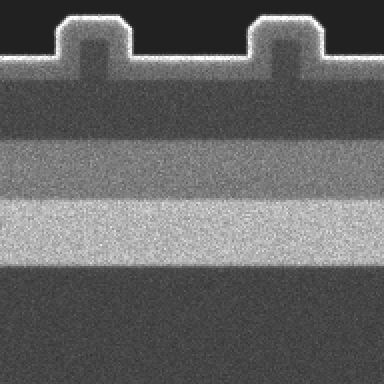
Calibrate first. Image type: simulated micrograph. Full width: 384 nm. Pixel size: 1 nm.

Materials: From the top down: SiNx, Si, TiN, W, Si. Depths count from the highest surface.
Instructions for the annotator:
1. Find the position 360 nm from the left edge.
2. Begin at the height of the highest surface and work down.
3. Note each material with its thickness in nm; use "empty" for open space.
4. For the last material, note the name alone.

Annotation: empty 40, SiNx 24, Si 60, TiN 60, W 66, Si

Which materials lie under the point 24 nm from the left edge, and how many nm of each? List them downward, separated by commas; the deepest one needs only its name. empty 40, SiNx 24, Si 60, TiN 60, W 66, Si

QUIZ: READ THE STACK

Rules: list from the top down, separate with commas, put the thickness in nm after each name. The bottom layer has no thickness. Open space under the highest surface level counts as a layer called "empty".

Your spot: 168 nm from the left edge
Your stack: empty 40, SiNx 24, Si 60, TiN 60, W 66, Si